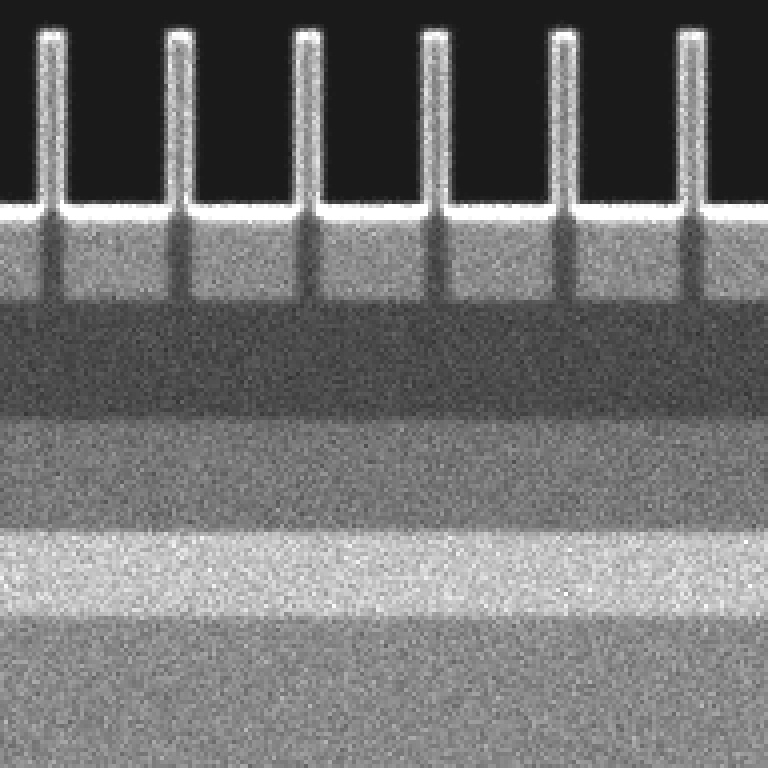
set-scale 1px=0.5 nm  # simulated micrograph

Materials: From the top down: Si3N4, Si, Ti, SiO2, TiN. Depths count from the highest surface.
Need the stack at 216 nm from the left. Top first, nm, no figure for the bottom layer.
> Si 194, Ti 56, SiO2 42, TiN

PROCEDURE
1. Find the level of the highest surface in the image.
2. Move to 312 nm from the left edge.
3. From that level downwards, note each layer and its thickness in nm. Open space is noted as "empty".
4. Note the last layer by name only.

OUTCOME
empty 88, Si3N4 46, Si 60, Ti 56, SiO2 42, TiN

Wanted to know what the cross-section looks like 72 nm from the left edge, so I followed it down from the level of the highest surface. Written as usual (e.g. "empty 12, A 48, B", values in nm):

empty 88, Si3N4 46, Si 60, Ti 56, SiO2 42, TiN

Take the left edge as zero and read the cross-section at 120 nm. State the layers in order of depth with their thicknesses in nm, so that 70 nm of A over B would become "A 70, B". empty 88, Si3N4 46, Si 60, Ti 56, SiO2 42, TiN